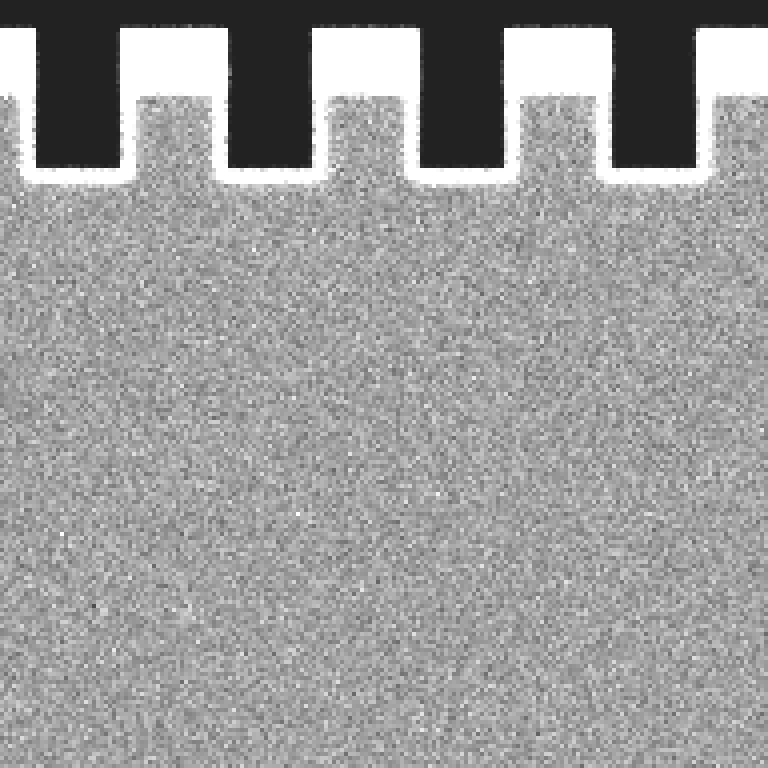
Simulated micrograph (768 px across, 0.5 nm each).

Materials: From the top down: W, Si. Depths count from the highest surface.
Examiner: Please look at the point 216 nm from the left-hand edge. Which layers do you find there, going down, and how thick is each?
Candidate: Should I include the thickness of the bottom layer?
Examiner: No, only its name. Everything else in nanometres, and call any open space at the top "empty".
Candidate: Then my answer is empty 70, Si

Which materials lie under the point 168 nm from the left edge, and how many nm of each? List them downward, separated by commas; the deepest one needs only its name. W 30, Si